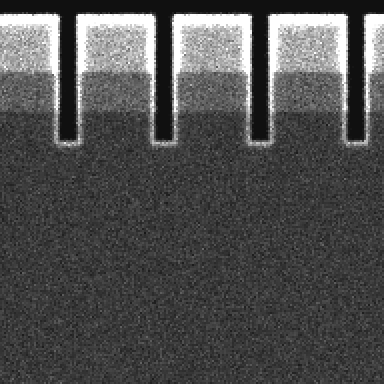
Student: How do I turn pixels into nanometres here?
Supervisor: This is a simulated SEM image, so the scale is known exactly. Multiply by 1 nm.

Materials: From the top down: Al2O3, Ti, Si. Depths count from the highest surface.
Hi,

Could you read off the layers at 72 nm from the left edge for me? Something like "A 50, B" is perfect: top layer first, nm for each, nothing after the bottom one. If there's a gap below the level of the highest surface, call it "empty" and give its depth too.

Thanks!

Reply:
empty 126, Si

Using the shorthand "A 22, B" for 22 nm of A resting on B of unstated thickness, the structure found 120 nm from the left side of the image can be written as Al2O3 56, Ti 40, Si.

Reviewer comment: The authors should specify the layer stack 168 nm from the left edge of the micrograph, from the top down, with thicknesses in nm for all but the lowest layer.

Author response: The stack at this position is empty 126, Si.